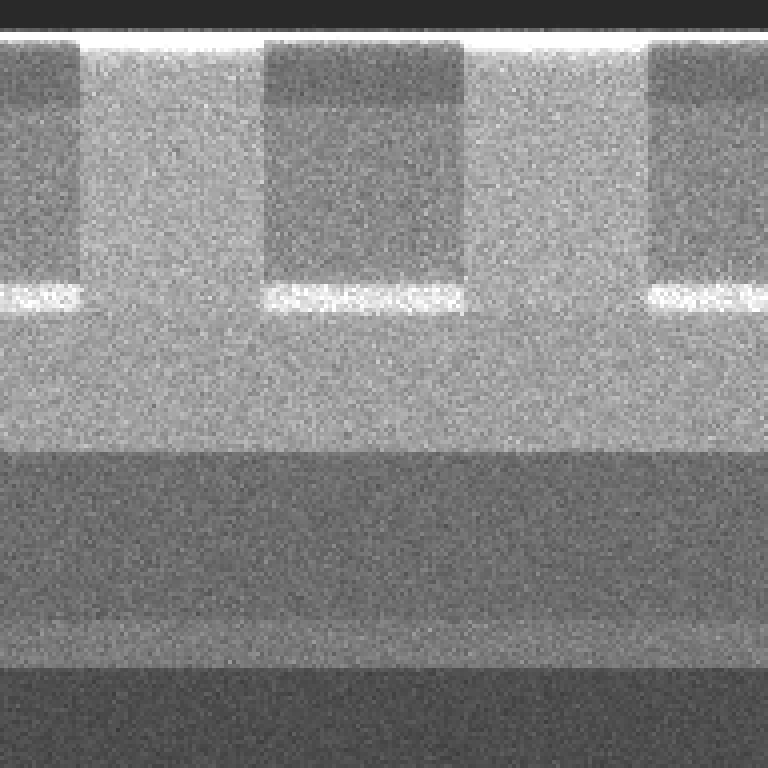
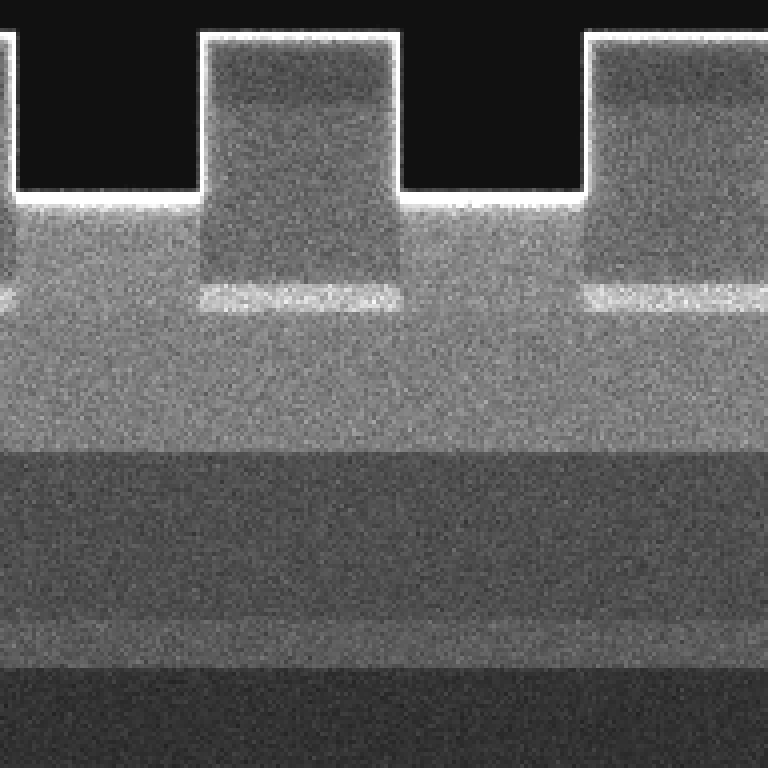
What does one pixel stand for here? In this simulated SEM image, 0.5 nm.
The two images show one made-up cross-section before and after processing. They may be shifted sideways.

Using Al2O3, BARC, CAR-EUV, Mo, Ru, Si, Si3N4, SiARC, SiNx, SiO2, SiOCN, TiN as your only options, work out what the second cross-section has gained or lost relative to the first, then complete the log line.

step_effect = removed Al2O3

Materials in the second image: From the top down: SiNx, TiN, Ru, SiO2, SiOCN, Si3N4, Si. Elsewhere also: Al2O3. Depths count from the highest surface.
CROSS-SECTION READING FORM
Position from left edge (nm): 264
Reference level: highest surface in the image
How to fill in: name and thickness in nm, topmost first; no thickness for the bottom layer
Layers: empty 80, Al2O3 60, SiO2 70, SiOCN 84, Si3N4 24, Si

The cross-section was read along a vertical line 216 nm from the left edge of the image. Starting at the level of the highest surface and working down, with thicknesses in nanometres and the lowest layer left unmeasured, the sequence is empty 80, Al2O3 60, SiO2 70, SiOCN 84, Si3N4 24, Si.